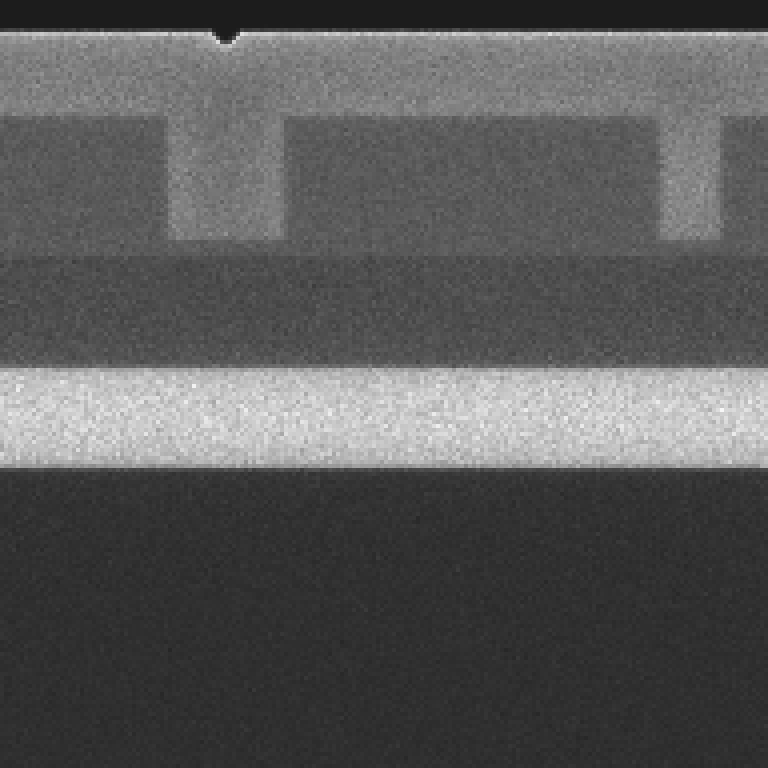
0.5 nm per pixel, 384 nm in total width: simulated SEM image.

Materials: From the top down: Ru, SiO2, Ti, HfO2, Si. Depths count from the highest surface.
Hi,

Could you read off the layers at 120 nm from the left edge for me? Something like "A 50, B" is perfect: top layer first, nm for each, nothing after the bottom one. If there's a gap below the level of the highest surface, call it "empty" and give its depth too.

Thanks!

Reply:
Ru 104, SiO2 8, Ti 56, HfO2 50, Si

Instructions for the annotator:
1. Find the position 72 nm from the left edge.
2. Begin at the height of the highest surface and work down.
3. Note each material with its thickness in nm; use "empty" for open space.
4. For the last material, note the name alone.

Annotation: Ru 42, SiO2 70, Ti 56, HfO2 50, Si